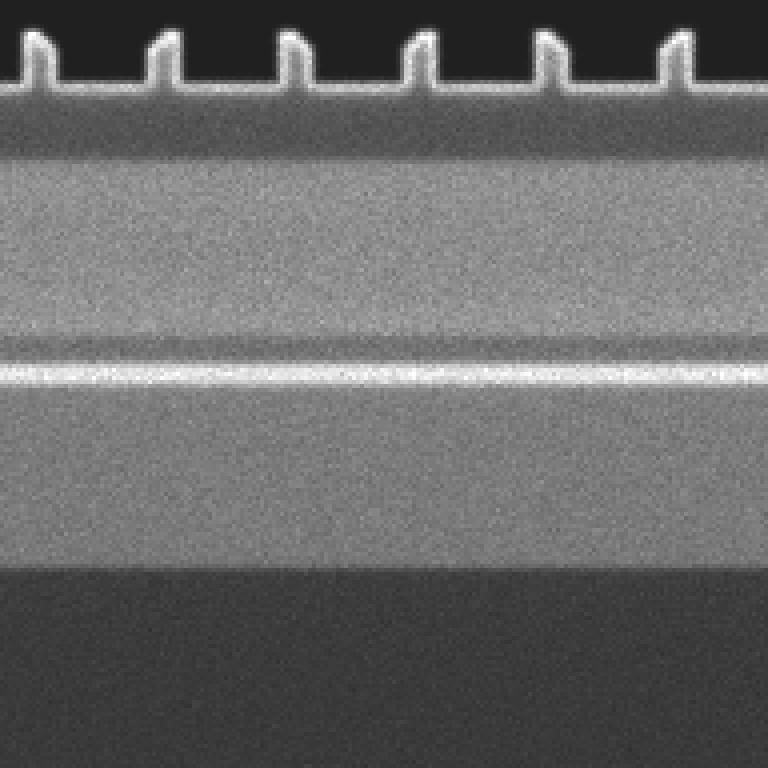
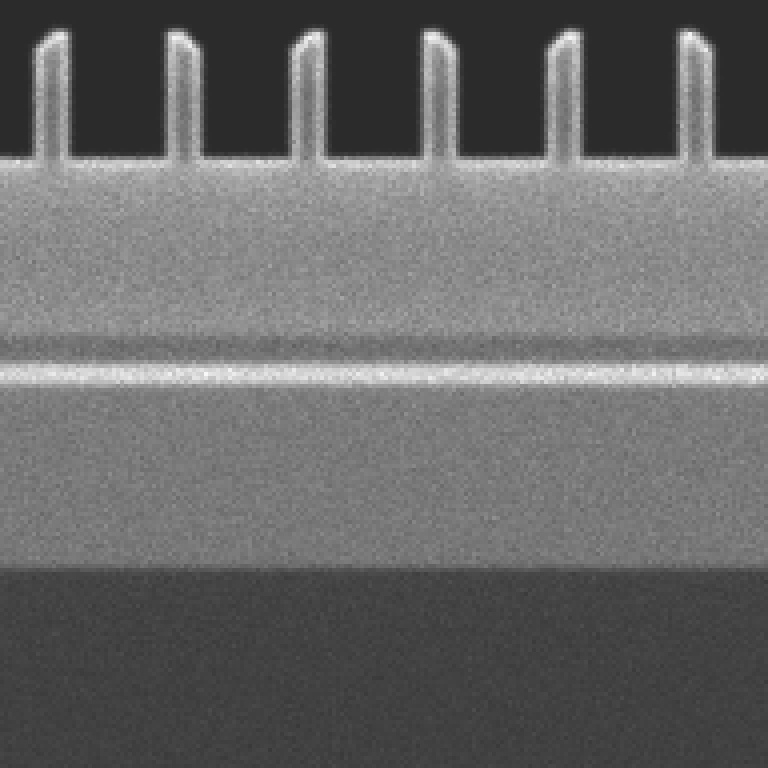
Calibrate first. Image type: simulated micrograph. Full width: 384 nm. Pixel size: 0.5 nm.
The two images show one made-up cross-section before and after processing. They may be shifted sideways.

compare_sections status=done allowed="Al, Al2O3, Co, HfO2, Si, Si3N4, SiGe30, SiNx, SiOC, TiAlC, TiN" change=removed material="SiNx"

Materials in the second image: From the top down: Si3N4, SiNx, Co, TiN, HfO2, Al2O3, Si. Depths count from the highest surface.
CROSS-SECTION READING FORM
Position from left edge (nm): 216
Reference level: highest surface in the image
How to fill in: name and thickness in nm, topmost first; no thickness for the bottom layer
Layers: Si3N4 26, SiNx 38, Co 88, TiN 14, HfO2 10, Al2O3 92, Si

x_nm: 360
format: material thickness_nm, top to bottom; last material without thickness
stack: empty 64, Co 88, TiN 14, HfO2 10, Al2O3 92, Si